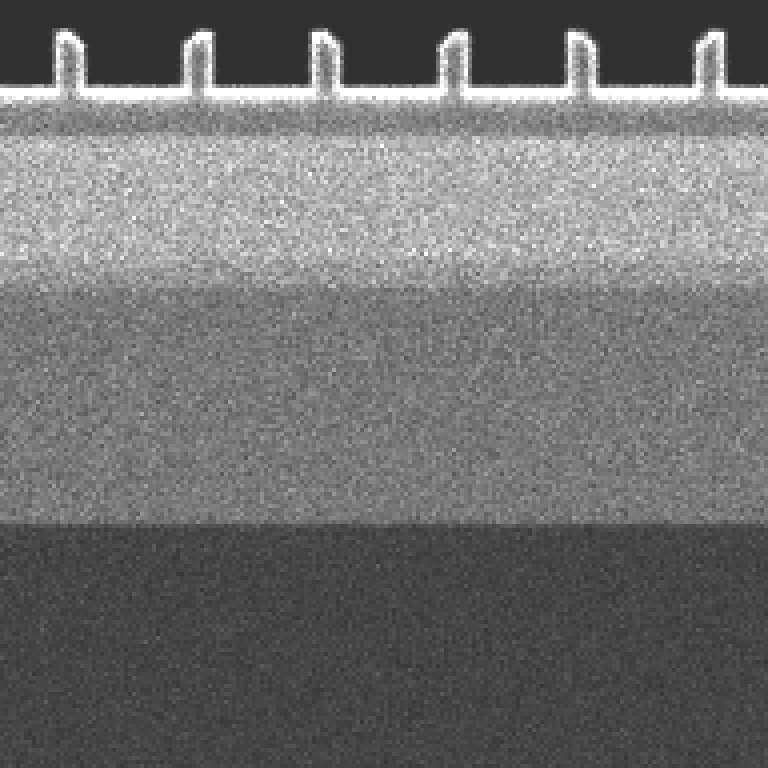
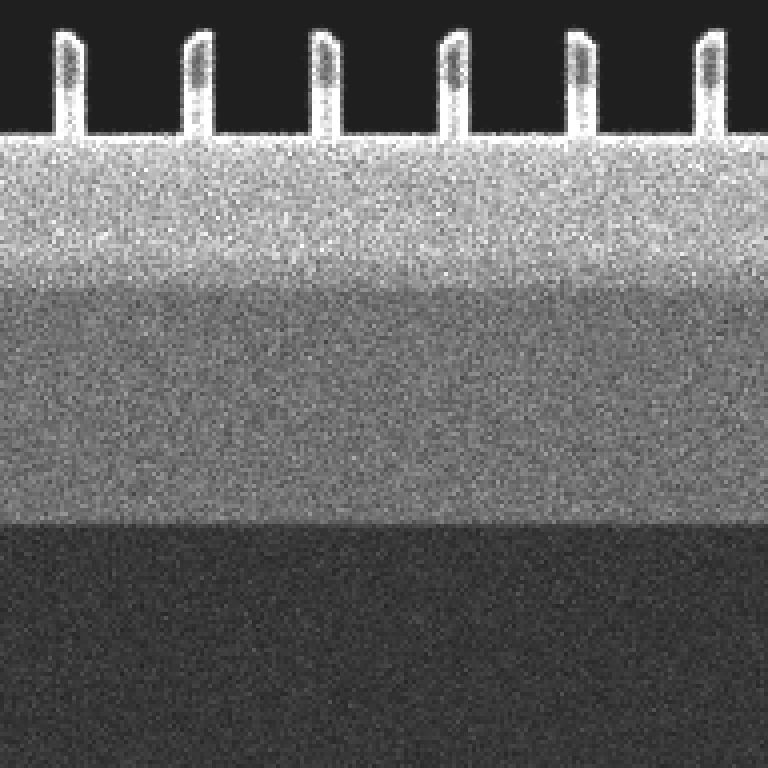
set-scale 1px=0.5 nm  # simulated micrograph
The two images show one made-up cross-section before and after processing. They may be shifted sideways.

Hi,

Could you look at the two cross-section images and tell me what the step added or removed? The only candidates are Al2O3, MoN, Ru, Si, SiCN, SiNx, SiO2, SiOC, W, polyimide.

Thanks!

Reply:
removed Al2O3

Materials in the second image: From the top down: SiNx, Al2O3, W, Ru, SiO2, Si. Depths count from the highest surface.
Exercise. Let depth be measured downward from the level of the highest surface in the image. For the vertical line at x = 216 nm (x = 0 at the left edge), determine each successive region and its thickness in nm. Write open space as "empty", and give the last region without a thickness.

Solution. empty 52, W 62, Ru 14, SiO2 118, Si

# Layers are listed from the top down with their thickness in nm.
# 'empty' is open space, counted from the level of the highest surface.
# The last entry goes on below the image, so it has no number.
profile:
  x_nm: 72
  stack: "empty 52, W 62, Ru 14, SiO2 118, Si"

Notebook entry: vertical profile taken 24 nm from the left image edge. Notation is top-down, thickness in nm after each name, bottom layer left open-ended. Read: empty 52, W 62, Ru 14, SiO2 118, Si